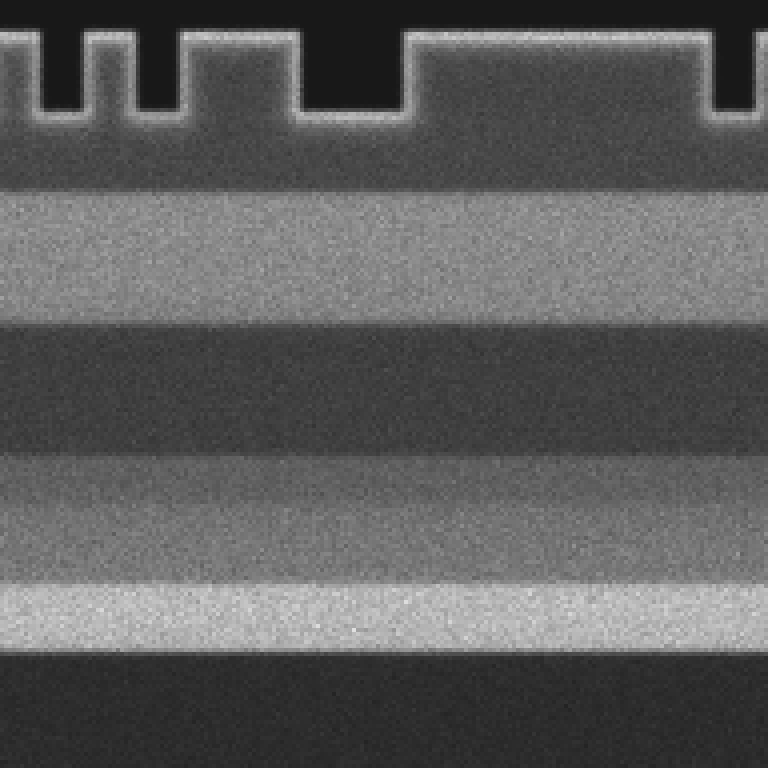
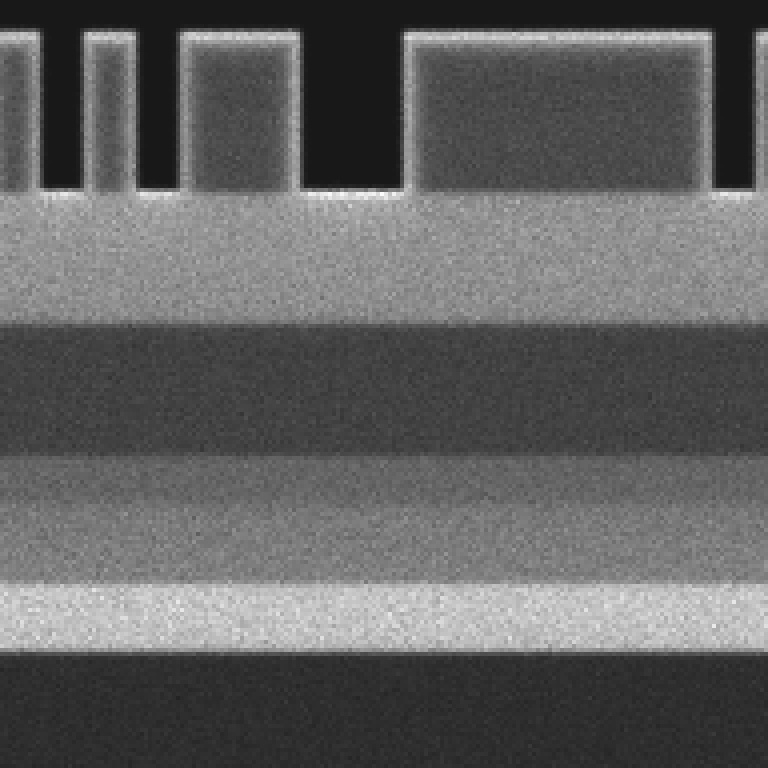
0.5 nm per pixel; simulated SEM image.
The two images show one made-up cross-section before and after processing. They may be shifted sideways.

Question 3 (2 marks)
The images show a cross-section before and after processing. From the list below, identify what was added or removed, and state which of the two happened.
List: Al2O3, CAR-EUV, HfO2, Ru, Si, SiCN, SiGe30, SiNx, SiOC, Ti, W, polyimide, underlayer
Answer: underlayer was removed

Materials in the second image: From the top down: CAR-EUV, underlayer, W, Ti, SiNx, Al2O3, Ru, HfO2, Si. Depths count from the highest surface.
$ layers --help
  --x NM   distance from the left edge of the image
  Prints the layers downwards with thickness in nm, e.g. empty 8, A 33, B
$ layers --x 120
CAR-EUV 40, underlayer 40, W 66, Ti 18, SiNx 48, Al2O3 24, Ru 40, HfO2 34, Si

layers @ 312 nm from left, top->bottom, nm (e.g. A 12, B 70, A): CAR-EUV 40, underlayer 40, W 66, Ti 18, SiNx 48, Al2O3 24, Ru 40, HfO2 34, Si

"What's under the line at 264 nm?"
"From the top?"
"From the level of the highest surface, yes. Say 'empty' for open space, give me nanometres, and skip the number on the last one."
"CAR-EUV 40, underlayer 40, W 66, Ti 18, SiNx 48, Al2O3 24, Ru 40, HfO2 34, Si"